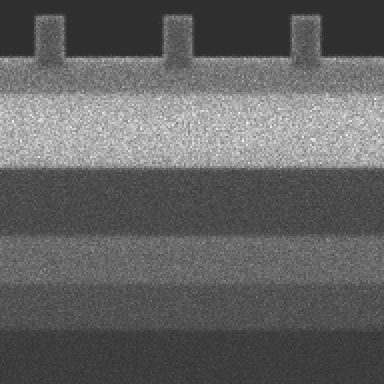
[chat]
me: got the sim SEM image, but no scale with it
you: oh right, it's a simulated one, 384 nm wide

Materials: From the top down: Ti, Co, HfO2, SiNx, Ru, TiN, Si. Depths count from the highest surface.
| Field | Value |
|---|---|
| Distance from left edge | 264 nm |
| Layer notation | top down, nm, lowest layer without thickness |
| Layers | empty 42, Co 36, HfO2 74, SiNx 68, Ru 48, TiN 46, Si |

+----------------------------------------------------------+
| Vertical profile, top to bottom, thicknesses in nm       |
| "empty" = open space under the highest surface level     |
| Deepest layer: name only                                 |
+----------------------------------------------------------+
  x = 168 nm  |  Ti 52, Co 26, HfO2 74, SiNx 68, Ru 48, TiN 46, Si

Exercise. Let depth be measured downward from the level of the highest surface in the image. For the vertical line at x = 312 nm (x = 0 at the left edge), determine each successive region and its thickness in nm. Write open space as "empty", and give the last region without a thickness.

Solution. Ti 52, Co 26, HfO2 74, SiNx 68, Ru 48, TiN 46, Si